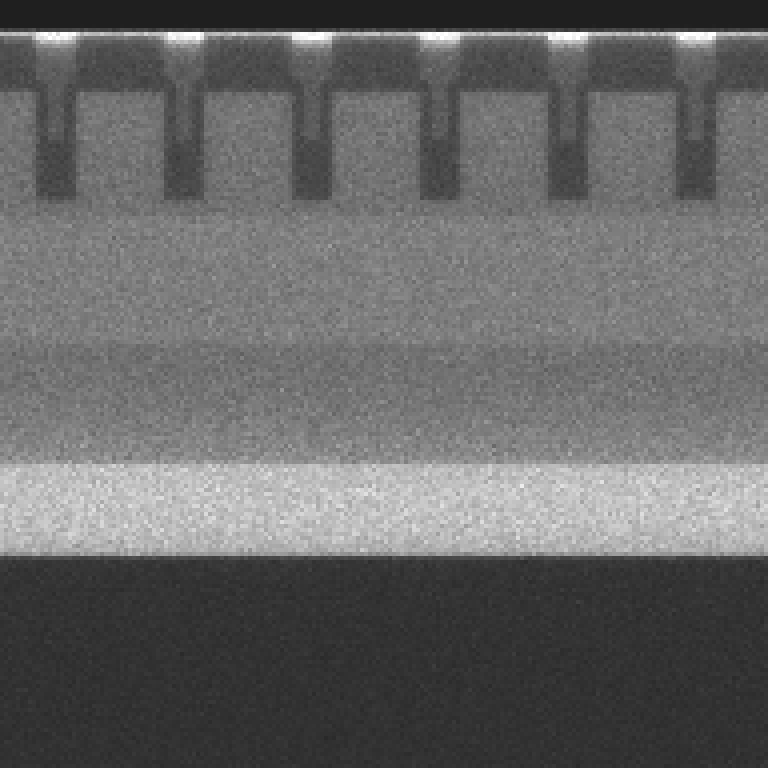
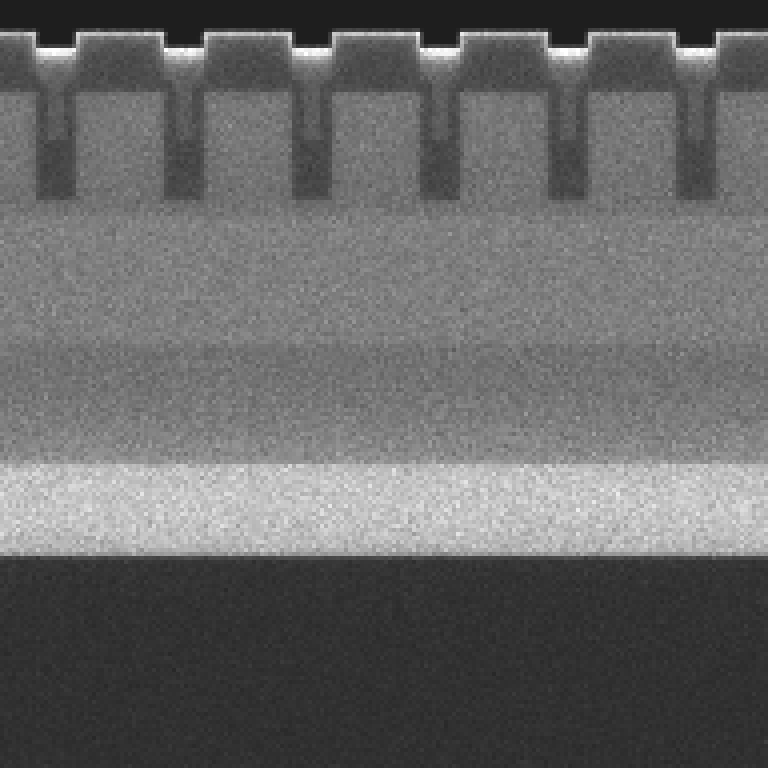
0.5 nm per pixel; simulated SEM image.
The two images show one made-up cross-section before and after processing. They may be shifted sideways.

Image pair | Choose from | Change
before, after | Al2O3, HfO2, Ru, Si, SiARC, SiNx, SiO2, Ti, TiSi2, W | SiO2 (removed)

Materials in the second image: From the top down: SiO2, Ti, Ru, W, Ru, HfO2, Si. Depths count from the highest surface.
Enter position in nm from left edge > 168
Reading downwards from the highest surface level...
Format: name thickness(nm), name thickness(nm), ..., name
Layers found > Ti 30, Ru 62, W 64, Ru 60, HfO2 46, Si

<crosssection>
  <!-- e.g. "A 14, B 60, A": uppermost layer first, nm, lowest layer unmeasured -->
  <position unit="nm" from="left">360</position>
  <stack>Ti 30, Ru 62, W 64, Ru 60, HfO2 46, Si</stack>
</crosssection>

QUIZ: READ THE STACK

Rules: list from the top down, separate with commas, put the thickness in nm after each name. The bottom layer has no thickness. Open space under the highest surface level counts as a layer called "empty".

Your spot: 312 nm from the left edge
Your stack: Ti 30, Ru 62, W 64, Ru 60, HfO2 46, Si